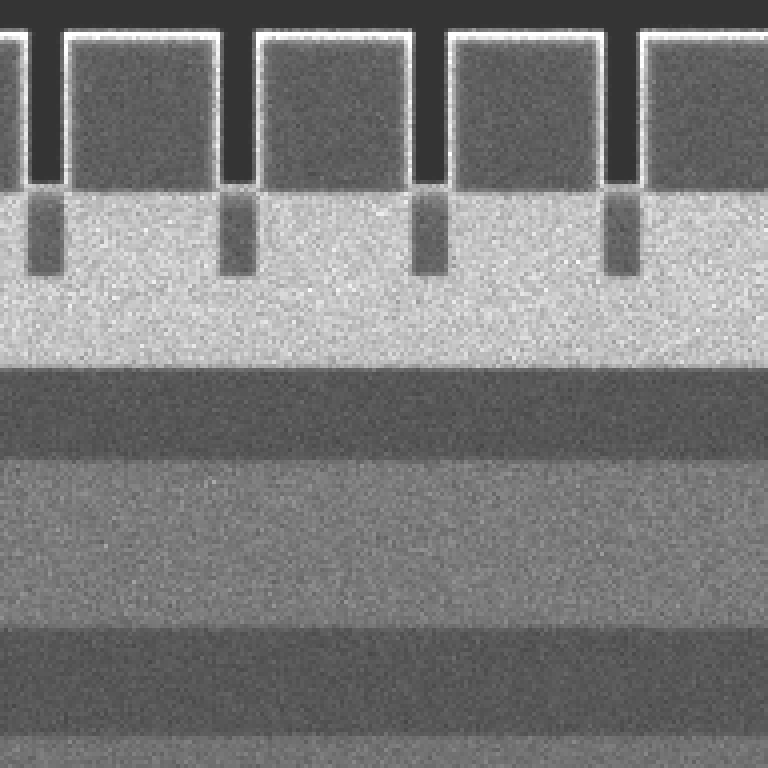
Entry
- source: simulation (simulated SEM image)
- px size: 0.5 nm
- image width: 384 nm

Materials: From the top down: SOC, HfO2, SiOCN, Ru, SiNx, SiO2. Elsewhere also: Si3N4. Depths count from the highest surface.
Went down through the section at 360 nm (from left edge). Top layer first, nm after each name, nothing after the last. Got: Si3N4 80, HfO2 88, SiOCN 46, Ru 84, SiNx 54, SiO2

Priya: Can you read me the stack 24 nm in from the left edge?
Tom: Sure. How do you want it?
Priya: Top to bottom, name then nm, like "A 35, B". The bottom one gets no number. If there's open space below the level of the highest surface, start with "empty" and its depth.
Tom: empty 76, SOC 46, HfO2 46, SiOCN 46, Ru 84, SiNx 54, SiO2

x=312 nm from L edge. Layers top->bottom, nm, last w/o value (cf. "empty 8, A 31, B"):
empty 76, SOC 46, HfO2 46, SiOCN 46, Ru 84, SiNx 54, SiO2